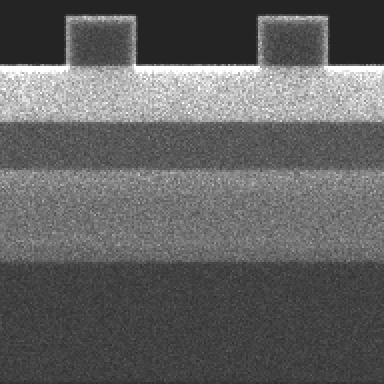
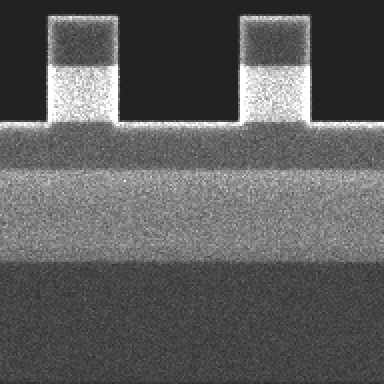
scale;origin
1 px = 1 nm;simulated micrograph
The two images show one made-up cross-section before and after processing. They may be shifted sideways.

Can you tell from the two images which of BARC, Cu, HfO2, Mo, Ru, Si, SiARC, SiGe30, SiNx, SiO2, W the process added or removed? Yes, it removed HfO2.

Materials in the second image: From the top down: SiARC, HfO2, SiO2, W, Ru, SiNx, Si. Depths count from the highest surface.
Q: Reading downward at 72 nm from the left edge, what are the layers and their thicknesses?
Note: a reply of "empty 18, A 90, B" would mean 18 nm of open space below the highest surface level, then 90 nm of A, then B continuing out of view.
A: SiARC 50, HfO2 56, SiO2 48, W 78, Ru 14, SiNx 120, Si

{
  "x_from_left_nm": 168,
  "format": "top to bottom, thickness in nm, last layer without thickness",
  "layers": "empty 106, SiO2 48, W 78, Ru 14, SiNx 120, Si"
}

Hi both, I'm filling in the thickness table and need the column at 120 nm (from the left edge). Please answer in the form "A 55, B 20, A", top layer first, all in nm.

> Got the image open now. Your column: empty 106, SiO2 48, W 78, Ru 14, SiNx 120, Si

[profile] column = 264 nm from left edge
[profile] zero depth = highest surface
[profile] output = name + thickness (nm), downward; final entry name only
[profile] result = SiARC 50, HfO2 56, SiO2 48, W 78, Ru 14, SiNx 120, Si